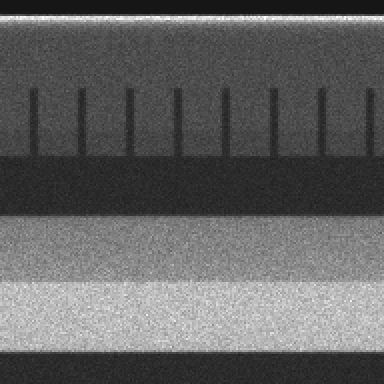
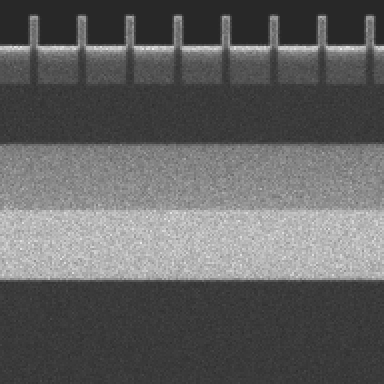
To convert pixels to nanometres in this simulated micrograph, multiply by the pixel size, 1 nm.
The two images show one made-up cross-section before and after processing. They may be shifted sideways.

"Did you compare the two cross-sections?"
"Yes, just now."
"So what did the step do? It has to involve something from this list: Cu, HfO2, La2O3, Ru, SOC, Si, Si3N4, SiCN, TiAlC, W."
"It removed SOC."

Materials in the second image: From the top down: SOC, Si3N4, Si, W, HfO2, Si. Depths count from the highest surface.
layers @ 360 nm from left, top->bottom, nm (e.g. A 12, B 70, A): empty 30, SOC 12, Si3N4 26, Si 60, W 66, HfO2 70, Si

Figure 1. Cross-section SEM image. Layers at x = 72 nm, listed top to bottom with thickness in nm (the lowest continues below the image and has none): empty 30, SOC 12, Si3N4 26, Si 60, W 66, HfO2 70, Si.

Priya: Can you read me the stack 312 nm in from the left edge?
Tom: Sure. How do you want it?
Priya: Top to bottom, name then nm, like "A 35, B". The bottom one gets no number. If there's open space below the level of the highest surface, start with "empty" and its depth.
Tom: empty 30, SOC 12, Si3N4 26, Si 60, W 66, HfO2 70, Si